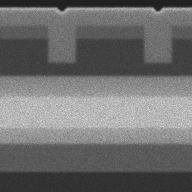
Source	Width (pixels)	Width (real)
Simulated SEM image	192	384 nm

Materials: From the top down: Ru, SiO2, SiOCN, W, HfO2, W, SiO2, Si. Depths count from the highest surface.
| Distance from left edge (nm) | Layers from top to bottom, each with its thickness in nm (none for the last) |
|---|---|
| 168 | Ru 36, SiO2 26, SiOCN 74, W 42, HfO2 62, W 32, SiO2 56, Si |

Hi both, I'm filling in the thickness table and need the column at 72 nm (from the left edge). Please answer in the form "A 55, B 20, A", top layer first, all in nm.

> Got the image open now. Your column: Ru 36, SiO2 26, SiOCN 74, W 42, HfO2 62, W 32, SiO2 56, Si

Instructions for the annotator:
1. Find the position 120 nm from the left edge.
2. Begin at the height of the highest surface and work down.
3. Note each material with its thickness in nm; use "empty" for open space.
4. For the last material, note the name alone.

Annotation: empty 8, Ru 102, SiOCN 26, W 42, HfO2 62, W 32, SiO2 56, Si